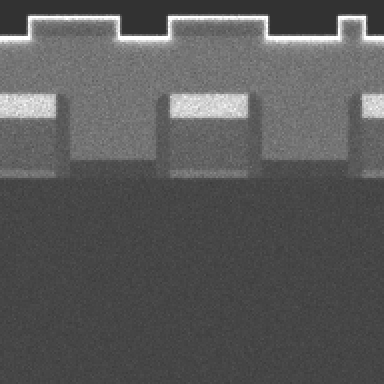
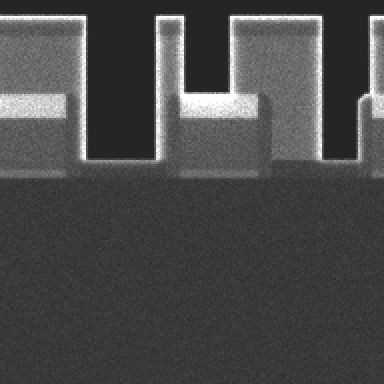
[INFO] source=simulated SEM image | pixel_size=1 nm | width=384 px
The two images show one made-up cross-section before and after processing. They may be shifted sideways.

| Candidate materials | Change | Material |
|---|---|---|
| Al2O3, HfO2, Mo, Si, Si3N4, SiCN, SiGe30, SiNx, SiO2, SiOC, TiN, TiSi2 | removed | SiO2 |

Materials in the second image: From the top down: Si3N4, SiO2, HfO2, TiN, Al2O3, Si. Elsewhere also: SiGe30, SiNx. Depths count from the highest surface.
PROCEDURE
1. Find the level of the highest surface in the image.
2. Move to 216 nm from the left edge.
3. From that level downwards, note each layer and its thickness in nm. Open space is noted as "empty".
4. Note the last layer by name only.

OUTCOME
empty 78, HfO2 24, TiN 52, Al2O3 8, Si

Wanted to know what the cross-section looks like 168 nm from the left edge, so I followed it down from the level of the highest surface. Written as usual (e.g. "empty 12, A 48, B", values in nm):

Si3N4 20, SiO2 62, SiNx 80, Si